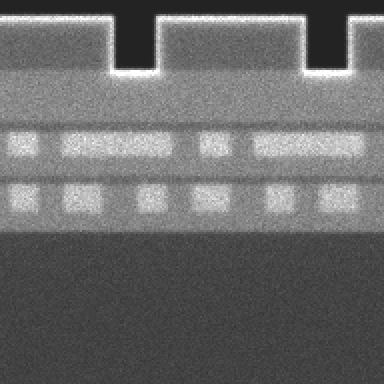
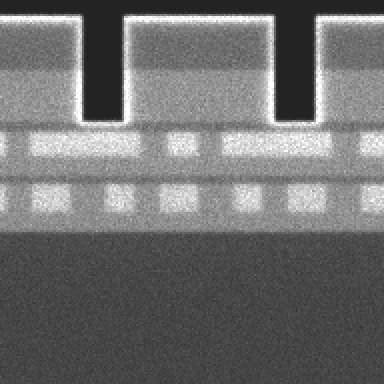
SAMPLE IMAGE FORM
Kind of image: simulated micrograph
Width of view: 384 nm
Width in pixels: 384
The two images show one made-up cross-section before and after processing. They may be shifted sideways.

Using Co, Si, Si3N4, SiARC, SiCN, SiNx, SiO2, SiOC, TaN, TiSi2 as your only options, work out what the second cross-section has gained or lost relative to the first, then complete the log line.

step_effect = removed SiO2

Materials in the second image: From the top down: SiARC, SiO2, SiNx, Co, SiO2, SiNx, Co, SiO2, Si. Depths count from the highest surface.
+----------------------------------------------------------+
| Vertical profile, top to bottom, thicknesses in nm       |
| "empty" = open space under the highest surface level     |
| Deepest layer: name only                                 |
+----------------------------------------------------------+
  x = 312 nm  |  empty 106, SiNx 10, Co 24, SiO2 20, SiNx 8, Co 28, SiO2 20, Si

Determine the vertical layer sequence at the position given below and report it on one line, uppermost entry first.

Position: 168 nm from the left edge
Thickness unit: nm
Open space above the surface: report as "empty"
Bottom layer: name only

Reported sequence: SiARC 54, SiO2 52, SiNx 10, Co 24, SiO2 20, SiNx 8, Co 28, SiO2 20, Si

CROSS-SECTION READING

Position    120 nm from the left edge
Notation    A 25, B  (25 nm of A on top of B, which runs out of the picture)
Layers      empty 106, SiNx 10, Co 24, SiO2 20, SiNx 8, Co 28, SiO2 20, Si